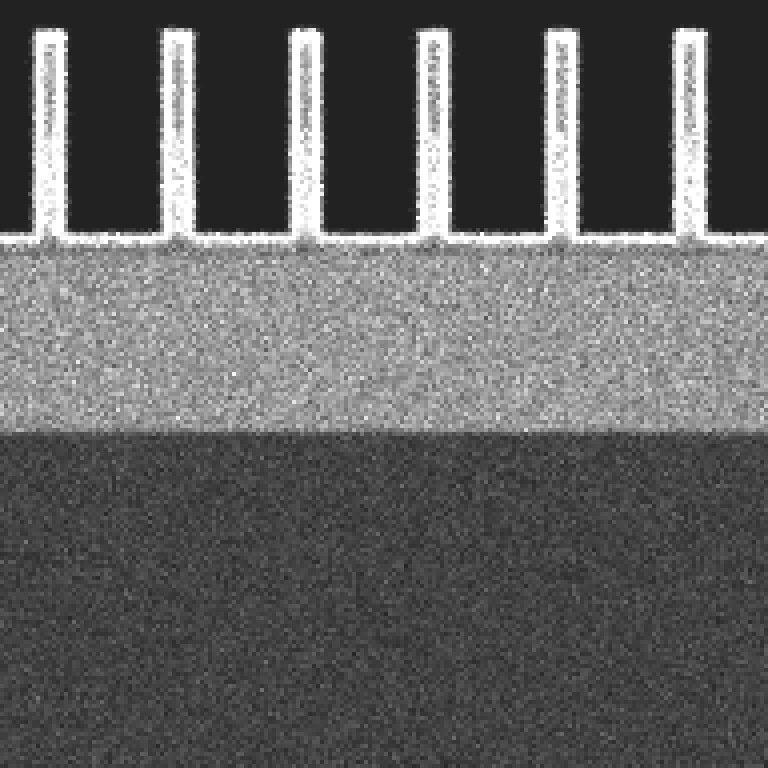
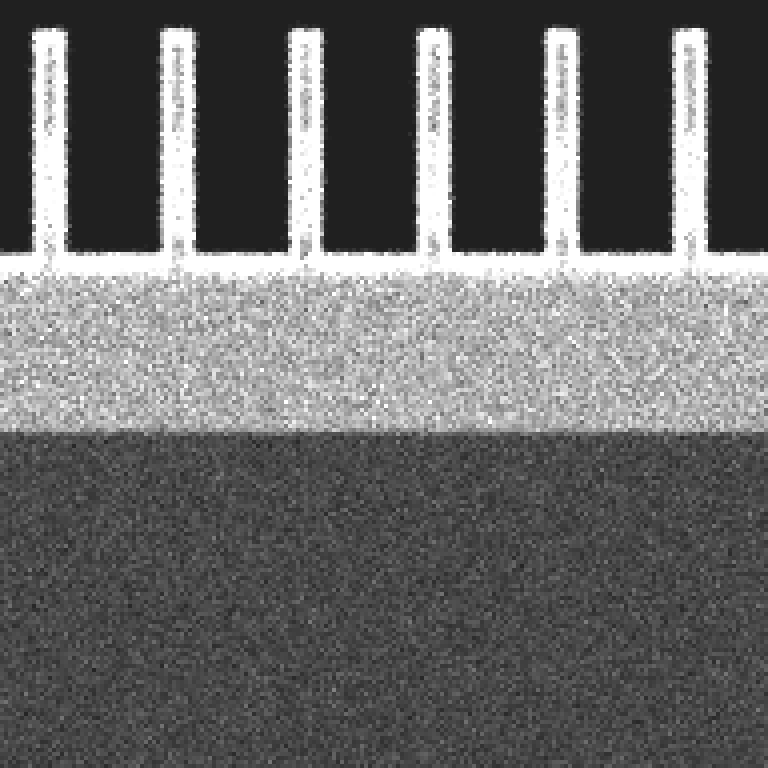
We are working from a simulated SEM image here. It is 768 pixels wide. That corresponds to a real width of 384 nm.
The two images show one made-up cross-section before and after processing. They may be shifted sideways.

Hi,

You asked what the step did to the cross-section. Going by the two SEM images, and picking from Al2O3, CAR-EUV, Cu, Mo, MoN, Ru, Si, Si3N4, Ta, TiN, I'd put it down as TiN, removed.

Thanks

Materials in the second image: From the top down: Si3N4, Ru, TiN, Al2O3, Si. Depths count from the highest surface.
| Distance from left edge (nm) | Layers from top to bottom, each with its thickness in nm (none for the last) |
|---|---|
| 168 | empty 112, Al2O3 88, Si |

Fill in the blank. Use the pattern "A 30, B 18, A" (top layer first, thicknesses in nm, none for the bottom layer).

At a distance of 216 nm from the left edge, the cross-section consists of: Si3N4 50, Ru 52, TiN 10, Al2O3 88, Si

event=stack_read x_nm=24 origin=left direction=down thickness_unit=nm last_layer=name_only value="Si3N4 50, Ru 52, TiN 10, Al2O3 88, Si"